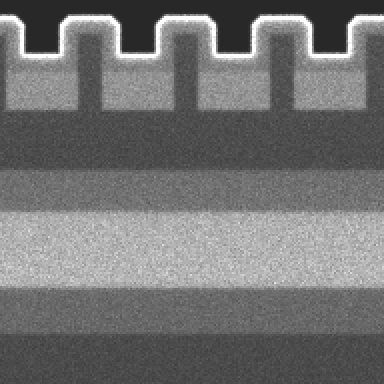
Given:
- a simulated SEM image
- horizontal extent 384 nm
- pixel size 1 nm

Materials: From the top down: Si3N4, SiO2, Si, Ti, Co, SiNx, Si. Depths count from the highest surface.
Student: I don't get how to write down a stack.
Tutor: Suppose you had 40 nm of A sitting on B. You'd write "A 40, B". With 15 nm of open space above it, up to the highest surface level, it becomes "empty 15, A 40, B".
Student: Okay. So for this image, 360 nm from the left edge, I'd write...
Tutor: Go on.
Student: Si3N4 56, SiO2 38, Si 60, Ti 42, Co 76, SiNx 46, Si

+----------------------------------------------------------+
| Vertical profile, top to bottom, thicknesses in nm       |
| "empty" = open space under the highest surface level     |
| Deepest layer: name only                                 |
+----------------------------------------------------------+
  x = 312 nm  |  empty 38, Si3N4 18, SiO2 38, Si 60, Ti 42, Co 76, SiNx 46, Si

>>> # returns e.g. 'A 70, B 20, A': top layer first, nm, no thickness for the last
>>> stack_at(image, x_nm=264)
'Si3N4 56, SiO2 38, Si 60, Ti 42, Co 76, SiNx 46, Si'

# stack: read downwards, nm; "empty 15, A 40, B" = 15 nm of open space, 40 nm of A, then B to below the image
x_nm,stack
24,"empty 38, Si3N4 18, SiO2 38, Si 60, Ti 42, Co 76, SiNx 46, Si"